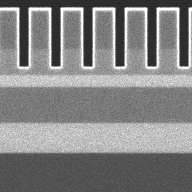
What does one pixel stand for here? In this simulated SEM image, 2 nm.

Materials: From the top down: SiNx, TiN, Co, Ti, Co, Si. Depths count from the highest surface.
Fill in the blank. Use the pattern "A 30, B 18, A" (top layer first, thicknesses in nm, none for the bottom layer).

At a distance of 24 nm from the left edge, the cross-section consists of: SiNx 82, TiN 52, Co 24, Ti 72, Co 60, Si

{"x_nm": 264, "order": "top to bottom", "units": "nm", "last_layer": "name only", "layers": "SiNx 82, TiN 52, Co 24, Ti 72, Co 60, Si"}